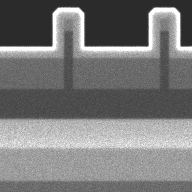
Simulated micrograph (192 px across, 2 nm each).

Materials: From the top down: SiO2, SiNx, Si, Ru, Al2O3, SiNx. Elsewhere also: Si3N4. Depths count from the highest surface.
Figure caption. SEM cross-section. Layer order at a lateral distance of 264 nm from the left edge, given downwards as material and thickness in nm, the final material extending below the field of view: empty 78, SiO2 22, SiNx 62, Si 60, Ru 58, Al2O3 66, SiNx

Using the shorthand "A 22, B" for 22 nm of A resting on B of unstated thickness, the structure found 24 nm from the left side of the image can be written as empty 78, SiO2 22, SiNx 62, Si 60, Ru 58, Al2O3 66, SiNx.